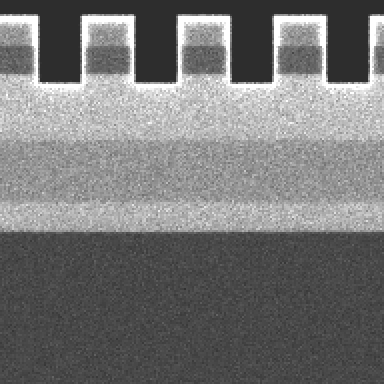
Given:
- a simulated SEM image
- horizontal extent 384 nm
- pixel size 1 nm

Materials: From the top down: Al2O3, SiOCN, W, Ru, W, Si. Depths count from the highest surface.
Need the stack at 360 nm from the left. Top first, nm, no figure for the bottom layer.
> empty 68, W 56, Ru 62, W 30, Si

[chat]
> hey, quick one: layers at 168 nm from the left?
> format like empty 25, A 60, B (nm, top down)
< empty 68, W 56, Ru 62, W 30, Si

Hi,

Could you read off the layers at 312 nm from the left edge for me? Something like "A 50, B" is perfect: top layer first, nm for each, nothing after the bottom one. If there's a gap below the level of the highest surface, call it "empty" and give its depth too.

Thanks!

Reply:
Al2O3 30, SiOCN 28, W 66, Ru 62, W 30, Si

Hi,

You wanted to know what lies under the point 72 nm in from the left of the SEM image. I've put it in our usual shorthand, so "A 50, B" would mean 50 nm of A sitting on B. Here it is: empty 68, W 56, Ru 62, W 30, Si